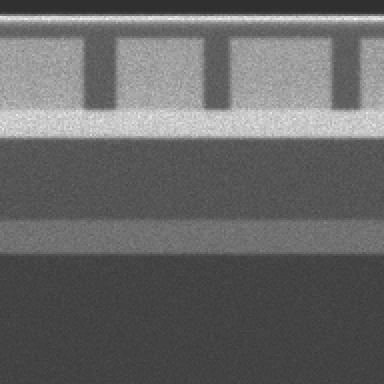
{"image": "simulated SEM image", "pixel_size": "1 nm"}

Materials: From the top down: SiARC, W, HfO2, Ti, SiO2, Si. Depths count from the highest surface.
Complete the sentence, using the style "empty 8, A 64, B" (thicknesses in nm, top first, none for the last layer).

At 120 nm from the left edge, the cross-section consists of SiARC 22, W 72, HfO2 28, Ti 82, SiO2 34, Si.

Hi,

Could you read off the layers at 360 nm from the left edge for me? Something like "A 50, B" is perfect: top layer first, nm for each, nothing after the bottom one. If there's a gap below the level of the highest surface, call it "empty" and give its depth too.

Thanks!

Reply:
SiARC 22, W 72, HfO2 28, Ti 82, SiO2 34, Si